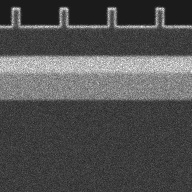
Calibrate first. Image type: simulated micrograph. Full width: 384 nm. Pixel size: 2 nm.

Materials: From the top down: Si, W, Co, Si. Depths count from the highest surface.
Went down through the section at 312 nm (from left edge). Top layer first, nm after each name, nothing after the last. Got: Si 96, W 34, Co 54, Si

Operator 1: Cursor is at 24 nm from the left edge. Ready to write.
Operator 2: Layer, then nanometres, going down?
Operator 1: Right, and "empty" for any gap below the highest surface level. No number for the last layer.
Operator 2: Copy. Si 96, W 34, Co 54, Si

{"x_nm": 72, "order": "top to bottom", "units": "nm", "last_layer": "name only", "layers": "empty 36, Si 60, W 34, Co 54, Si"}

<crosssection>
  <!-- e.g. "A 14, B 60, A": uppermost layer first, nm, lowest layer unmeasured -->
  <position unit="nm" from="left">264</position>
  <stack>empty 36, Si 60, W 34, Co 54, Si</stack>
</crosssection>